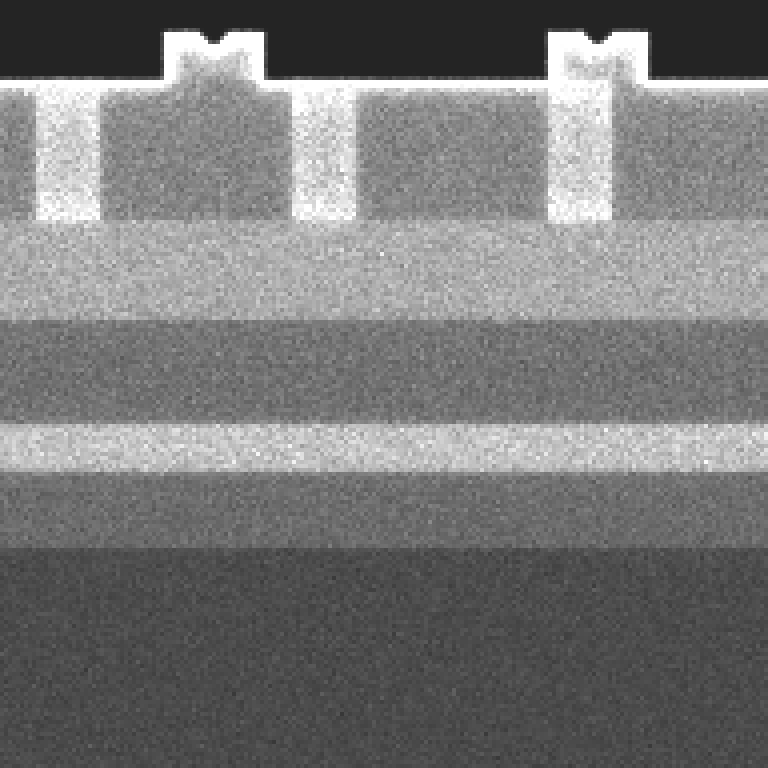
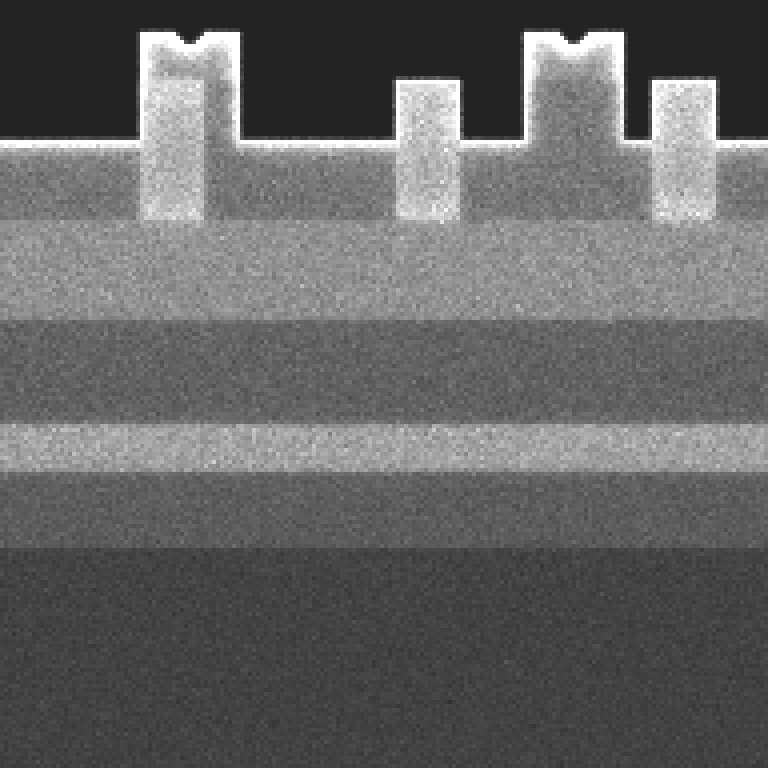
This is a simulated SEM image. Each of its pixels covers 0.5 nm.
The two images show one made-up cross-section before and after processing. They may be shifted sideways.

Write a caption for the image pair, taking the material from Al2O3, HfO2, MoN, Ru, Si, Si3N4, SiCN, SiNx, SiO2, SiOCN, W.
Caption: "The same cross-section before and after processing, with Si3N4 removed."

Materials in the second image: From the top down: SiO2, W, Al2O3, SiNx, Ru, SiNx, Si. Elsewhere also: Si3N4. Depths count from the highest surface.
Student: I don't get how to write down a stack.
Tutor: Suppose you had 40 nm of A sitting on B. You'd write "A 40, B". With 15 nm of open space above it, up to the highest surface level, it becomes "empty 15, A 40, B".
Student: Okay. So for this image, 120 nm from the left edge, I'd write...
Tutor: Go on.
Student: empty 54, Si3N4 40, Al2O3 50, SiNx 52, Ru 24, SiNx 38, Si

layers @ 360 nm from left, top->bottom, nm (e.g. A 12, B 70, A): empty 54, Si3N4 40, Al2O3 50, SiNx 52, Ru 24, SiNx 38, Si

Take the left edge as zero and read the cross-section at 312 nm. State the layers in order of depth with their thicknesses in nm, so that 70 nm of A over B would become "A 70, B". empty 54, Si3N4 40, Al2O3 50, SiNx 52, Ru 24, SiNx 38, Si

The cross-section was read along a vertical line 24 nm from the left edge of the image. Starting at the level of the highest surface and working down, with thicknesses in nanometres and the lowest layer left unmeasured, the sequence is empty 54, Si3N4 40, Al2O3 50, SiNx 52, Ru 24, SiNx 38, Si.